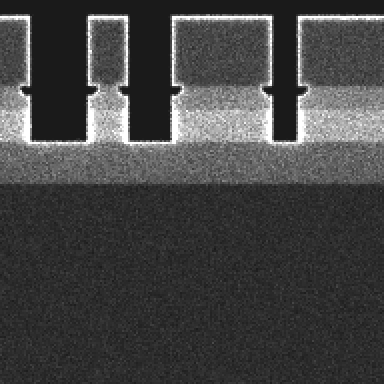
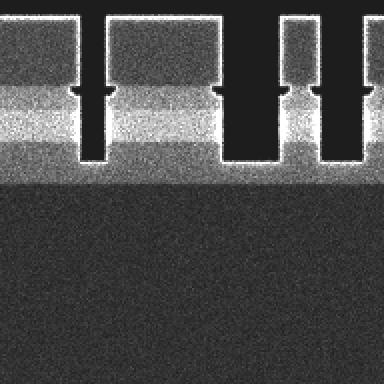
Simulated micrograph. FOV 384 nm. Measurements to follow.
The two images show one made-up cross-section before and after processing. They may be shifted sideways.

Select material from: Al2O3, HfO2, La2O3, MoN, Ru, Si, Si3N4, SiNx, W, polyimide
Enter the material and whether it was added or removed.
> Ru / removed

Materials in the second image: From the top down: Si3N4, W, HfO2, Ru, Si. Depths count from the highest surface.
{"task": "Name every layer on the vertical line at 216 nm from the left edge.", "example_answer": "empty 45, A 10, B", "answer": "Si3N4 70, empty 10, W 14, HfO2 32, Ru 42, Si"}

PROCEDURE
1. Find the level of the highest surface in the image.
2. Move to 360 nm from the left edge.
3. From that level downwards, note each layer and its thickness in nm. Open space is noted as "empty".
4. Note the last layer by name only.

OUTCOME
empty 146, Ru 22, Si